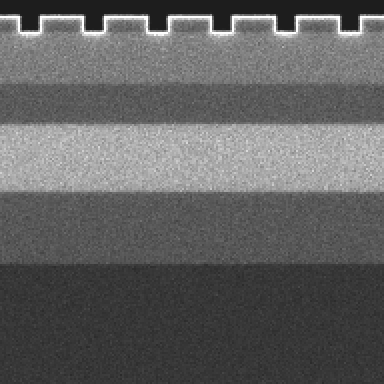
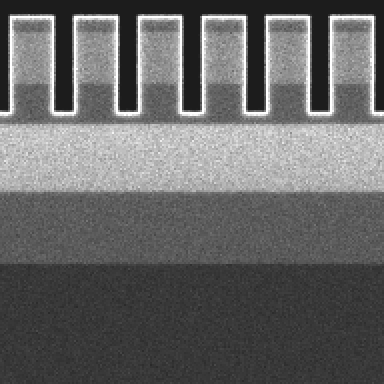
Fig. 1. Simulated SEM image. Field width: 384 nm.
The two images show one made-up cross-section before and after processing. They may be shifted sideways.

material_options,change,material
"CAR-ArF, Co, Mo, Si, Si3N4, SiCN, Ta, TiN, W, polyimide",removed,Co and Si3N4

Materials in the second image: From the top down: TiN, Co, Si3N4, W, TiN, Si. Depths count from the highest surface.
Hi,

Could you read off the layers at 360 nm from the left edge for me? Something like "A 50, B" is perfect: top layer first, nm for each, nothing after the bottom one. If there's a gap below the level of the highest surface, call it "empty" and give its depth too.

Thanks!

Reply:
TiN 16, Co 52, Si3N4 40, W 68, TiN 72, Si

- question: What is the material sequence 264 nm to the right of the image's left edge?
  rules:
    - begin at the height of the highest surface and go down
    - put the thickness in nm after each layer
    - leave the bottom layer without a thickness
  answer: empty 96, Si3N4 12, W 68, TiN 72, Si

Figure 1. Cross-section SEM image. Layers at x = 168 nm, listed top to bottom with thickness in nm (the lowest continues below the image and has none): TiN 16, Co 52, Si3N4 40, W 68, TiN 72, Si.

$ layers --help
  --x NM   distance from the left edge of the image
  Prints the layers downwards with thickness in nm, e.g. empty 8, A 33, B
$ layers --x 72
empty 96, Si3N4 12, W 68, TiN 72, Si